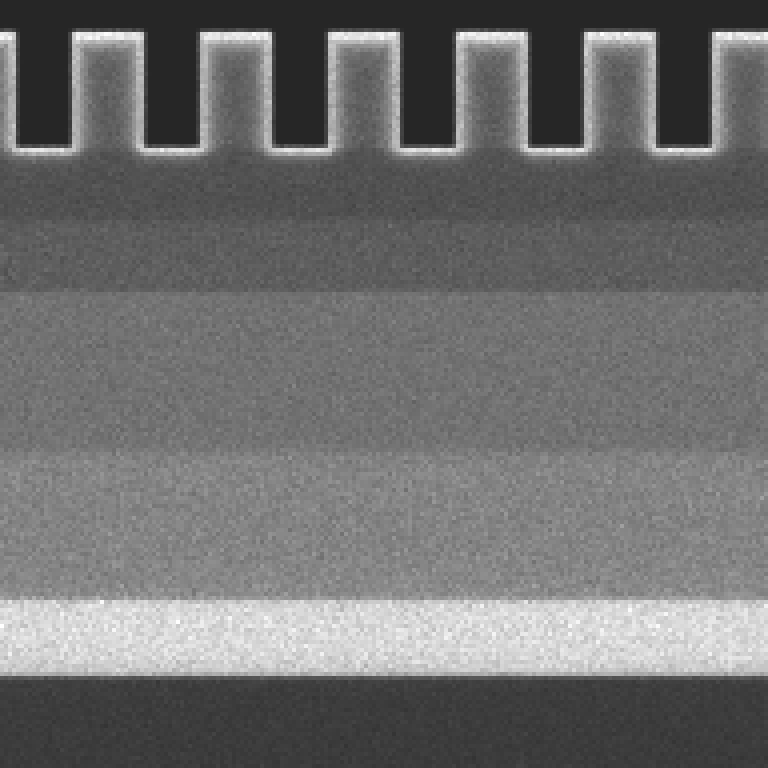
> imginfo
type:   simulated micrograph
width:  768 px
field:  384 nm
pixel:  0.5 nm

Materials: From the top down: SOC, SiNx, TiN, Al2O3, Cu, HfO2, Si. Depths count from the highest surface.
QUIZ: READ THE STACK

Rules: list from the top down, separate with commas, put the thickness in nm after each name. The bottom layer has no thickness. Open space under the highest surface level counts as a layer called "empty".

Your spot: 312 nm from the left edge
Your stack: SOC 58, SiNx 36, TiN 36, Al2O3 80, Cu 74, HfO2 38, Si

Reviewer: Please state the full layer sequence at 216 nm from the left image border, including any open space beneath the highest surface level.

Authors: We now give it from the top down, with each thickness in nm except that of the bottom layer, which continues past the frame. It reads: empty 58, SiNx 36, TiN 36, Al2O3 80, Cu 74, HfO2 38, Si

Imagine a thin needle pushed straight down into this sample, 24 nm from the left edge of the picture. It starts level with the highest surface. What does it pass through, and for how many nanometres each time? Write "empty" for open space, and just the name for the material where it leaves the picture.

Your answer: empty 58, SiNx 36, TiN 36, Al2O3 80, Cu 74, HfO2 38, Si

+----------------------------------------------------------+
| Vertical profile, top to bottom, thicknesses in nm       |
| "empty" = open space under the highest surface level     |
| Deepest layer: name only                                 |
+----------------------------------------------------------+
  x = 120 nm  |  SOC 58, SiNx 36, TiN 36, Al2O3 80, Cu 74, HfO2 38, Si